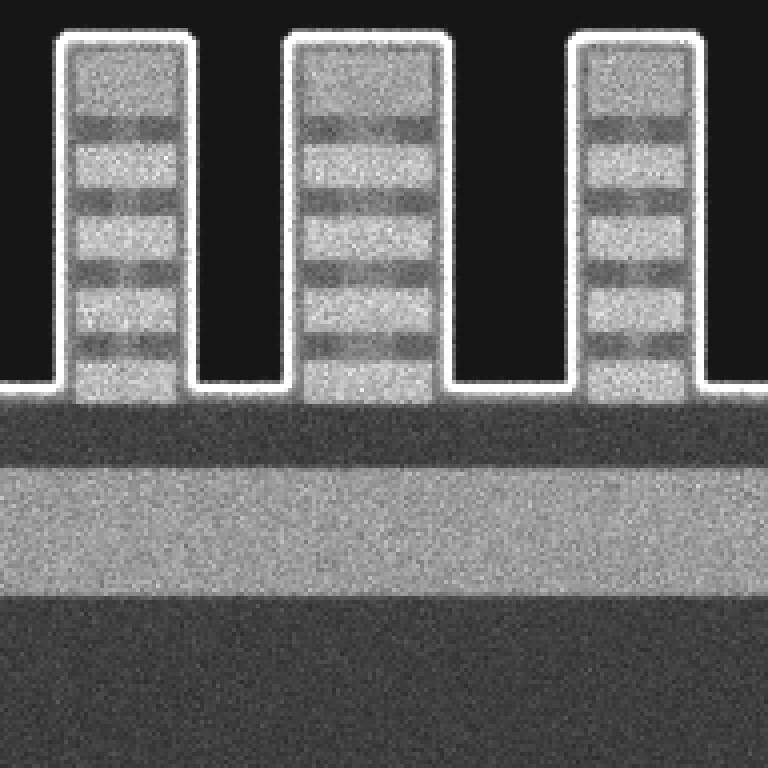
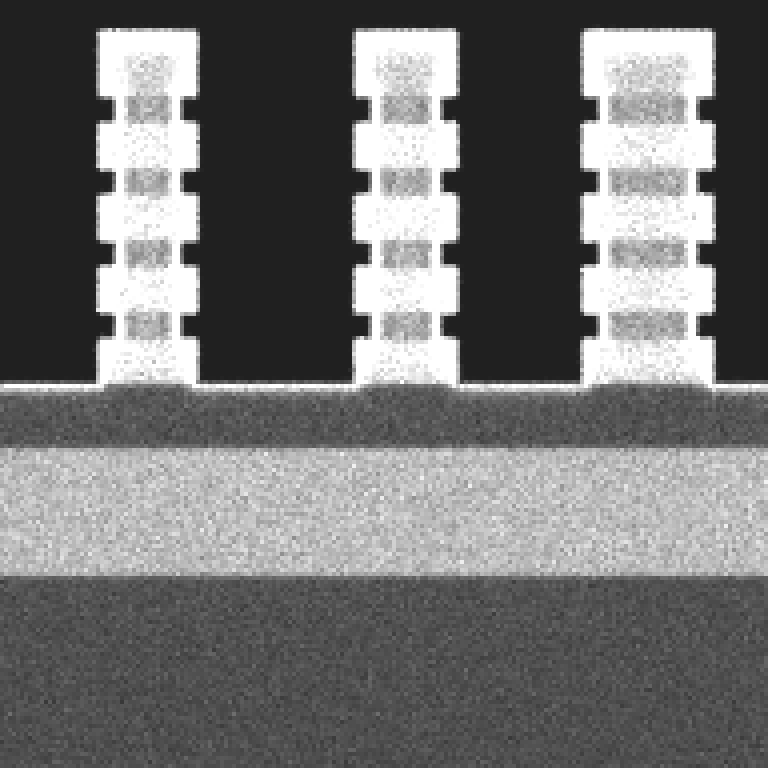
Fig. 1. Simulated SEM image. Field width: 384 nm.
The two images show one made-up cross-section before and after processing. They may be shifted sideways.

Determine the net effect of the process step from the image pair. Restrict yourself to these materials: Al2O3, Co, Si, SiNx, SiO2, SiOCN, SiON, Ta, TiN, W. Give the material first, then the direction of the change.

SiOCN: removed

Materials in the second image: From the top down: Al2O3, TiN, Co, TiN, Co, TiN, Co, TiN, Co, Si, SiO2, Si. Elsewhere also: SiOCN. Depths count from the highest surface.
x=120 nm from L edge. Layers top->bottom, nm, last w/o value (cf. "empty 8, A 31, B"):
empty 176, Si 32, SiO2 64, Si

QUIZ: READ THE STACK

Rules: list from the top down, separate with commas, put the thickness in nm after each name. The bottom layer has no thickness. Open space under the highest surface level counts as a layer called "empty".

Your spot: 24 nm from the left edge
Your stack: empty 176, Si 32, SiO2 64, Si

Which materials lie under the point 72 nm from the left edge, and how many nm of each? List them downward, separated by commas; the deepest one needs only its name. Al2O3 32, TiN 14, Co 22, TiN 14, Co 22, TiN 14, Co 22, TiN 14, Co 22, Si 32, SiO2 64, Si